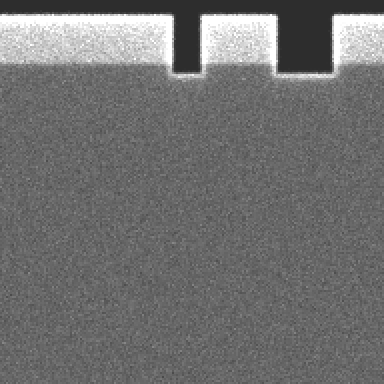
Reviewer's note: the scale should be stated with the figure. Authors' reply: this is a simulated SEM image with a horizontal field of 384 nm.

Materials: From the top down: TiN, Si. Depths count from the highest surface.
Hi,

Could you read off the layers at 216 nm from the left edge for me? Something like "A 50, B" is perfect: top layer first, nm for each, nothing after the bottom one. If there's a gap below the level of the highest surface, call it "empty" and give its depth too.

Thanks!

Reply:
TiN 48, Si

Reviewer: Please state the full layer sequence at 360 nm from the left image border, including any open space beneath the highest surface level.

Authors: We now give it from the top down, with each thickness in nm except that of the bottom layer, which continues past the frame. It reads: TiN 48, Si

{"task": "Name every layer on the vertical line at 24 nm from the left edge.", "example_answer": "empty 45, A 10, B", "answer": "TiN 48, Si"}